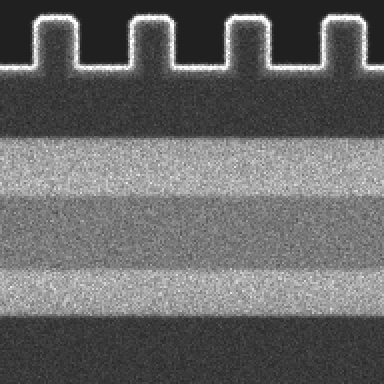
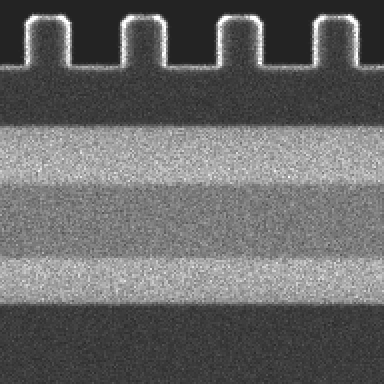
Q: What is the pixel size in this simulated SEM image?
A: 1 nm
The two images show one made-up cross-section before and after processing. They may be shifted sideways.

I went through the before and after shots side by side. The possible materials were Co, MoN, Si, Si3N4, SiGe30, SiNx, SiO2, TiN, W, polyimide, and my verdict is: removed, SiNx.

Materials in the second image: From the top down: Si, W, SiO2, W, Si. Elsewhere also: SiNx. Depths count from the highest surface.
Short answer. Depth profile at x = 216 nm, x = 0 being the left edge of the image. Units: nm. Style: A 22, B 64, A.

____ empty 50, Si 60, W 58, SiO2 74, W 46, Si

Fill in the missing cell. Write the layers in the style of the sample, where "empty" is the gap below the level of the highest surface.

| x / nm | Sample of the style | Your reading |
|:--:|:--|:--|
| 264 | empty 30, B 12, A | empty 50, Si 60, W 58, SiO2 74, W 46, Si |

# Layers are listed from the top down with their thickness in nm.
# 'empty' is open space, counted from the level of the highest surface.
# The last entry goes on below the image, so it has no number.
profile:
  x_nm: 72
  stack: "empty 50, Si 60, W 58, SiO2 74, W 46, Si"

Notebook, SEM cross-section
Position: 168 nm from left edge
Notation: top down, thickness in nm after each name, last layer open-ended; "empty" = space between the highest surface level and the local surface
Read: empty 50, Si 60, W 58, SiO2 74, W 46, Si